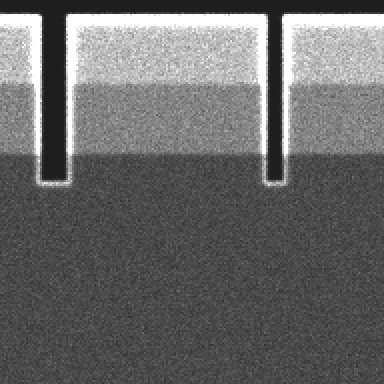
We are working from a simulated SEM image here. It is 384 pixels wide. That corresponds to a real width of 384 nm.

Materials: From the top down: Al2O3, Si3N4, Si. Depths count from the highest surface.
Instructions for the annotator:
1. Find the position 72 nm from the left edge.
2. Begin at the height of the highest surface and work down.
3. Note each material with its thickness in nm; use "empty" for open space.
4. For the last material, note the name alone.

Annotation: Al2O3 68, Si3N4 70, Si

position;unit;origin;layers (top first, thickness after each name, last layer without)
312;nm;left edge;Al2O3 68, Si3N4 70, Si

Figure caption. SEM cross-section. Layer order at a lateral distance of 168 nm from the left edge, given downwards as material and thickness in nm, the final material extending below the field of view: Al2O3 68, Si3N4 70, Si